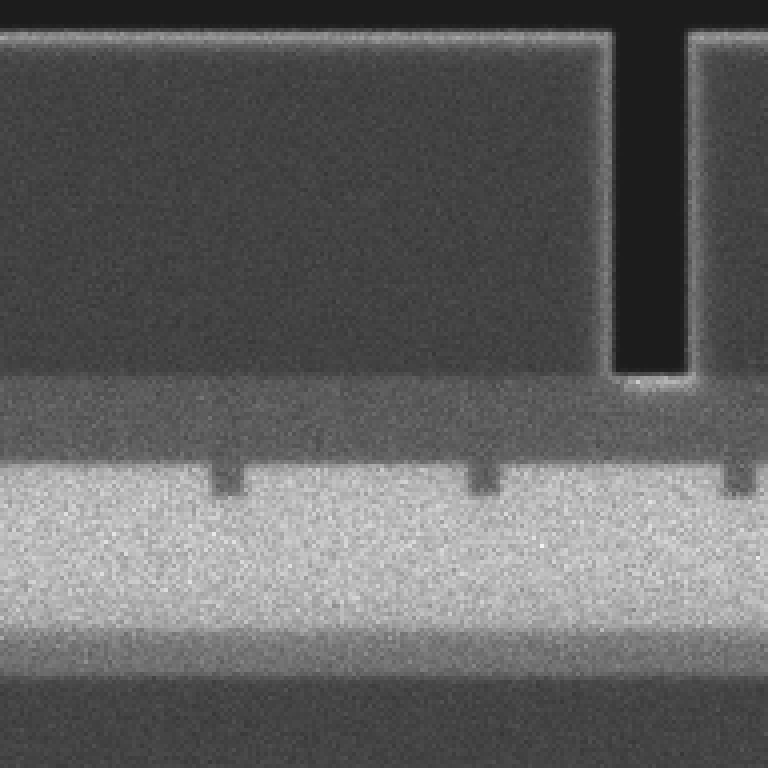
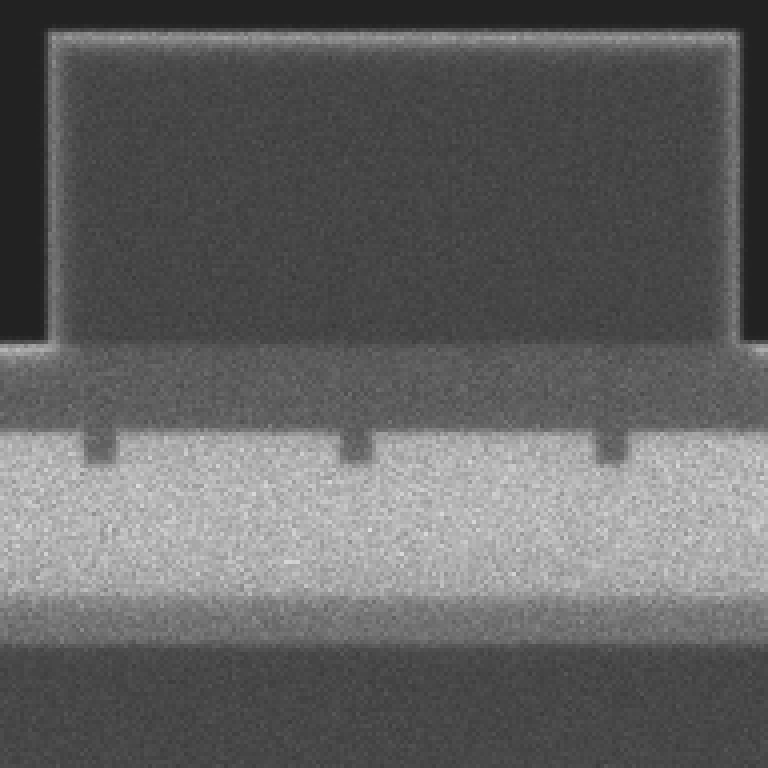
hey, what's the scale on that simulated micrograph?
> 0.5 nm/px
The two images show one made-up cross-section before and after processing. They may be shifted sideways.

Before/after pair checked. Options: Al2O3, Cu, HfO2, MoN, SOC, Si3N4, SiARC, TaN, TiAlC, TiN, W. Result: removed SiARC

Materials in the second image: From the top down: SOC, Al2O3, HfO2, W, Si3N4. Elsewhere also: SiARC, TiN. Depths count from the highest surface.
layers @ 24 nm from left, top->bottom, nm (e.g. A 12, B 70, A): SOC 156, Al2O3 44, HfO2 82, W 24, Si3N4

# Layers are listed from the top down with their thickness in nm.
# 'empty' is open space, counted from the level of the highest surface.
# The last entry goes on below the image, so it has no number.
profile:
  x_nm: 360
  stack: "SOC 156, Al2O3 44, HfO2 82, W 24, Si3N4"